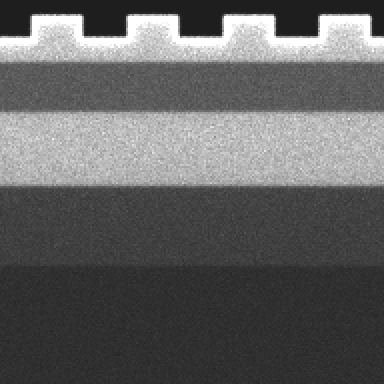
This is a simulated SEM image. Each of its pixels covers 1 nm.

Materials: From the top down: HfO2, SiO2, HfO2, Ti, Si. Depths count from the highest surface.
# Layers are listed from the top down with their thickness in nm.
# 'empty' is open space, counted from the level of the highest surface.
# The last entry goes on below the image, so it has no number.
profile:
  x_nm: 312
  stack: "empty 22, HfO2 24, SiO2 50, HfO2 74, Ti 80, Si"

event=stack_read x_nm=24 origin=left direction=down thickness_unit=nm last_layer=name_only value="empty 22, HfO2 24, SiO2 50, HfO2 74, Ti 80, Si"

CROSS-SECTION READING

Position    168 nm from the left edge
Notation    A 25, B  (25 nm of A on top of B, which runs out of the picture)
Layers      HfO2 46, SiO2 50, HfO2 74, Ti 80, Si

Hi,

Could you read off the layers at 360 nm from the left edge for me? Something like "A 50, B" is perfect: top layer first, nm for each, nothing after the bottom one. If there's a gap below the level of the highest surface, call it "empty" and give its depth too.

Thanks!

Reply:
HfO2 46, SiO2 50, HfO2 74, Ti 80, Si